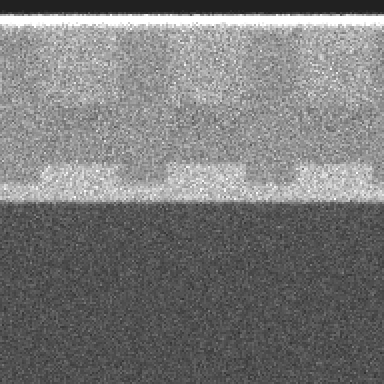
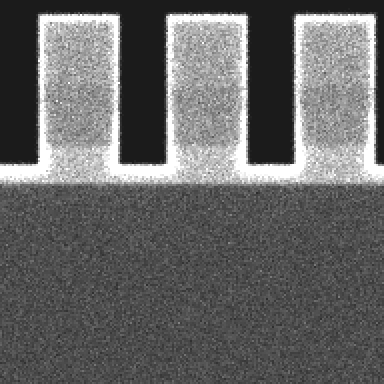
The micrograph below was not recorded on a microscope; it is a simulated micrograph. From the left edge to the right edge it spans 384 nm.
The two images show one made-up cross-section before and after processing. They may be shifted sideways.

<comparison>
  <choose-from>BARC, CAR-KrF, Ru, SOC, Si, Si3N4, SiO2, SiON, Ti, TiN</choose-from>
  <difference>SOC removed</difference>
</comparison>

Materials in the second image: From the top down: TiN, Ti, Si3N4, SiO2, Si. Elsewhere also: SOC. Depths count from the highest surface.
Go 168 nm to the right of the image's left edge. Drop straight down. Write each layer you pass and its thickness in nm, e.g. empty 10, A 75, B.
TiN 70, Ti 28, Si3N4 32, SiO2 38, Si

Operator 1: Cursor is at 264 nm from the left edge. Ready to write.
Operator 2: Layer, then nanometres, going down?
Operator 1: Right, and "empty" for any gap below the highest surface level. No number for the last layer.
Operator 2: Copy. empty 150, SiO2 18, Si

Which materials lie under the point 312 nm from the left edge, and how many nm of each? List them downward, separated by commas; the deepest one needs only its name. TiN 70, Ti 28, Si3N4 32, SiO2 38, Si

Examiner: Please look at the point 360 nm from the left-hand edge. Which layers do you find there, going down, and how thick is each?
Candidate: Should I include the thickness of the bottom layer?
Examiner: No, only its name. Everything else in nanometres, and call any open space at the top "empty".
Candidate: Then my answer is TiN 70, Ti 28, Si3N4 32, SiO2 38, Si